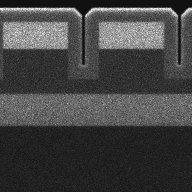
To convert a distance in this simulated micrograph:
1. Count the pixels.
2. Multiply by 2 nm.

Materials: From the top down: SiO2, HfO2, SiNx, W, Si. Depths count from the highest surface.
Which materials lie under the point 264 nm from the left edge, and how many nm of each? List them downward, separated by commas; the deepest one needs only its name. SiO2 28, HfO2 54, SiNx 90, W 64, Si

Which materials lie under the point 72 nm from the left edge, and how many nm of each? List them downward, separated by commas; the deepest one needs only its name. SiO2 28, HfO2 54, SiNx 90, W 64, Si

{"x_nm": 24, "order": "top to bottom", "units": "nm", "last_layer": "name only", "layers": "SiO2 28, HfO2 54, SiNx 90, W 64, Si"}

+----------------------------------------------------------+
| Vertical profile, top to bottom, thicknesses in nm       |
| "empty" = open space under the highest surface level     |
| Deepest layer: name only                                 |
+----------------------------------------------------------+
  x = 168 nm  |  empty 114, SiO2 28, SiNx 30, W 64, Si